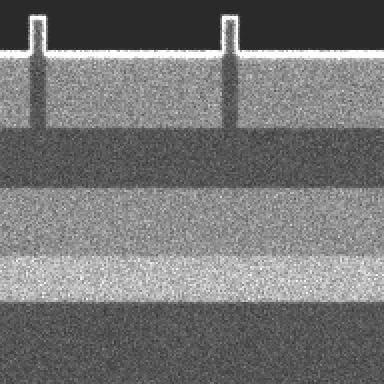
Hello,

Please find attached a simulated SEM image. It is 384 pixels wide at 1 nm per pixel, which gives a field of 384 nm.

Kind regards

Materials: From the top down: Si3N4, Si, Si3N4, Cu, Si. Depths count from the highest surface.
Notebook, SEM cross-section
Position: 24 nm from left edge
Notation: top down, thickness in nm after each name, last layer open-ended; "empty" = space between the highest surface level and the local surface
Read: empty 36, Si3N4 76, Si 60, Si3N4 68, Cu 46, Si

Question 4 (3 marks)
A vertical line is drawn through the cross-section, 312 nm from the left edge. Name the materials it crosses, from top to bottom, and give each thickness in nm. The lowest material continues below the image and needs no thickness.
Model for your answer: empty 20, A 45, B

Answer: empty 36, Si3N4 76, Si 60, Si3N4 68, Cu 46, Si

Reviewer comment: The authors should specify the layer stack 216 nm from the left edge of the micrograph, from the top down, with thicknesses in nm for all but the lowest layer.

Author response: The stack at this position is empty 36, Si3N4 76, Si 60, Si3N4 68, Cu 46, Si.